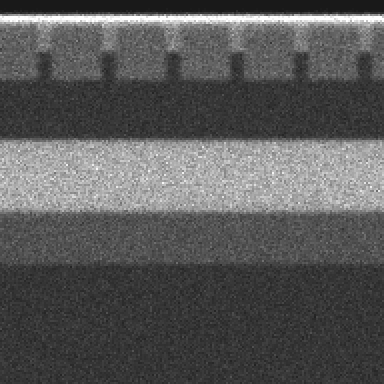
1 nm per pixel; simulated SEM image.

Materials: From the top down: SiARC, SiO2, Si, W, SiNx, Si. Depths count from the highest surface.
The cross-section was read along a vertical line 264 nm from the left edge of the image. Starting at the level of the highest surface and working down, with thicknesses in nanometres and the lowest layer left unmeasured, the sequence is SiARC 64, Si 60, W 72, SiNx 52, Si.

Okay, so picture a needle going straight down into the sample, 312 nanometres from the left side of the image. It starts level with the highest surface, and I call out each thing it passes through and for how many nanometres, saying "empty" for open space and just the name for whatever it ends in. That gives SiARC 64, Si 60, W 72, SiNx 52, Si